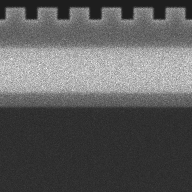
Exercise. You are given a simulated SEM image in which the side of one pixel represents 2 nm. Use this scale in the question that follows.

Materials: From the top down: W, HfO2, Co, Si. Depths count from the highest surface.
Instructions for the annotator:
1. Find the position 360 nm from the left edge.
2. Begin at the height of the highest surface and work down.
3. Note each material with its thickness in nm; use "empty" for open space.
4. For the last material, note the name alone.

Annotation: W 80, HfO2 90, Co 28, Si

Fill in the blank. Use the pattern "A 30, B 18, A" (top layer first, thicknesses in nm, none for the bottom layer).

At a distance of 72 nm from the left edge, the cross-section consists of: empty 24, W 56, HfO2 90, Co 28, Si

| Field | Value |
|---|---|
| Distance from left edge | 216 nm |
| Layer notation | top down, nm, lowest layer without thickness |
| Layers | W 80, HfO2 90, Co 28, Si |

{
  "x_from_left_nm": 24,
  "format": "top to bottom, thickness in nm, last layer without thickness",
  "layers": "W 80, HfO2 90, Co 28, Si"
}